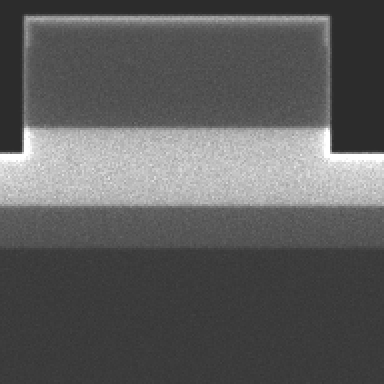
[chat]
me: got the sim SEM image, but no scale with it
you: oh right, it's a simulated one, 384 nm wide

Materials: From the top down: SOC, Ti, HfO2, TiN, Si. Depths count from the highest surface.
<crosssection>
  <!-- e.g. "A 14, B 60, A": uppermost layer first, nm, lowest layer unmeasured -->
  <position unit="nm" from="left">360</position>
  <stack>empty 138, HfO2 52, TiN 42, Si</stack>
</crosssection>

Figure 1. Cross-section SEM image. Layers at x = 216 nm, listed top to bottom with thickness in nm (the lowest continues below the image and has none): SOC 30, Ti 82, HfO2 78, TiN 42, Si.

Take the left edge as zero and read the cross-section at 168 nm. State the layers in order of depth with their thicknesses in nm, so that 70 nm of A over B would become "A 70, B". SOC 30, Ti 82, HfO2 78, TiN 42, Si